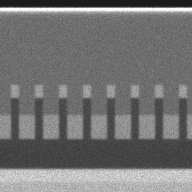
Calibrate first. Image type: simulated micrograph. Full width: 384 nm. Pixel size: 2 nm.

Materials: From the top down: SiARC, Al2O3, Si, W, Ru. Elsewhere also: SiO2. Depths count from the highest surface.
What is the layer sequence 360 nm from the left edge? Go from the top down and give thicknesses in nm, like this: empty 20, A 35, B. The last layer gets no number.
SiARC 154, Al2O3 26, Si 142, W 26, Ru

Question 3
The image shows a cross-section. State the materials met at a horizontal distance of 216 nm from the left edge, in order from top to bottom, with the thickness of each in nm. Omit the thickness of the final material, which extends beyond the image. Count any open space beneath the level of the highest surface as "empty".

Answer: SiARC 154, Al2O3 26, Si 142, W 26, Ru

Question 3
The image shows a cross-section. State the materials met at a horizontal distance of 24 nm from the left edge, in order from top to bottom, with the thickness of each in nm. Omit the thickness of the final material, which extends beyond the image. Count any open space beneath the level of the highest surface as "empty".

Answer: SiARC 154, Al2O3 26, Si 142, W 26, Ru